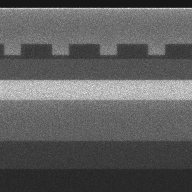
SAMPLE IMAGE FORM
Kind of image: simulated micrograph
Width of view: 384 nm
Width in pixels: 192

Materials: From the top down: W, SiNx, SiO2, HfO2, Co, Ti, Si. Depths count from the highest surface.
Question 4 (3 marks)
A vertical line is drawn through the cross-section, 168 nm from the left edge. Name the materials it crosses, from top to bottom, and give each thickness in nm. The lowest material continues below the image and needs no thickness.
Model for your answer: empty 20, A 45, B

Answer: W 72, SiNx 30, SiO2 42, HfO2 40, Co 82, Ti 56, Si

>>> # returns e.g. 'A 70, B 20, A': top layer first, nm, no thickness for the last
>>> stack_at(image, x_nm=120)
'W 94, SiNx 8, SiO2 42, HfO2 40, Co 82, Ti 56, Si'